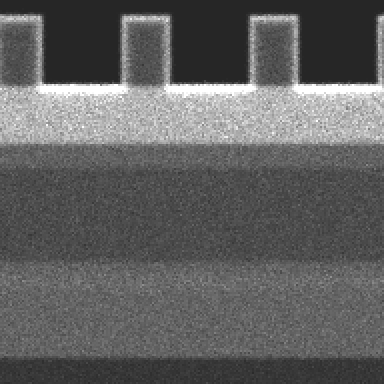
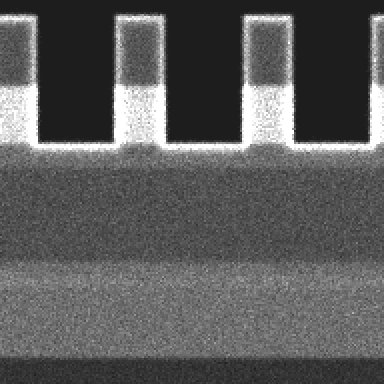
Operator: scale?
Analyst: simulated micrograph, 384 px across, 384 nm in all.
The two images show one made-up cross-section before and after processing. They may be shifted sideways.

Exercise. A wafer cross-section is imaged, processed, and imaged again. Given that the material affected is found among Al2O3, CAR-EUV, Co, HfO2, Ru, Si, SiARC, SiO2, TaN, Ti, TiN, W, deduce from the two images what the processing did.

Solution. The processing removed HfO2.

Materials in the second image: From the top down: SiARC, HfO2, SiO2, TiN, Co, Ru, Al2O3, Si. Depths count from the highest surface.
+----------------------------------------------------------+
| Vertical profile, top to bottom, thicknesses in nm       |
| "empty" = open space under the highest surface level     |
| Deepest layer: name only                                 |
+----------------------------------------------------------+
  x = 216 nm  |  empty 128, SiO2 24, TiN 94, Co 14, Ru 12, Al2O3 70, Si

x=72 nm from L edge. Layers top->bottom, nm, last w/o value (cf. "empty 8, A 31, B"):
empty 128, SiO2 24, TiN 94, Co 14, Ru 12, Al2O3 70, Si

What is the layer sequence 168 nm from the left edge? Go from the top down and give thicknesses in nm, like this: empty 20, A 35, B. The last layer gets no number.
empty 128, SiO2 24, TiN 94, Co 14, Ru 12, Al2O3 70, Si